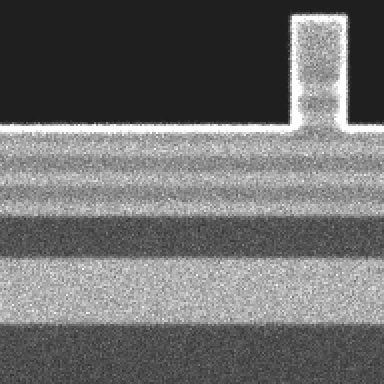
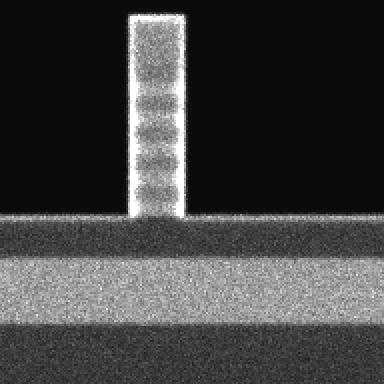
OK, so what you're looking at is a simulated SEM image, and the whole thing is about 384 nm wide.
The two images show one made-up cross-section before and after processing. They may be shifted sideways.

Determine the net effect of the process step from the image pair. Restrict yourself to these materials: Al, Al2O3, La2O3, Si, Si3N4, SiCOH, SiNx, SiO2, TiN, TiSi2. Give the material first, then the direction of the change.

Si3N4 and SiO2: removed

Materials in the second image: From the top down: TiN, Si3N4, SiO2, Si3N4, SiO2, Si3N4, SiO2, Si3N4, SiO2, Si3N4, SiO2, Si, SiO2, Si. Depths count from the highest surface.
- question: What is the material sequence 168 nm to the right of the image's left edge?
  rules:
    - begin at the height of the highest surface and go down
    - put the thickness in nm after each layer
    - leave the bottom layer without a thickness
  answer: TiN 50, Si3N4 16, SiO2 14, Si3N4 16, SiO2 14, Si3N4 16, SiO2 14, Si3N4 16, SiO2 14, Si3N4 16, SiO2 14, Si 42, SiO2 66, Si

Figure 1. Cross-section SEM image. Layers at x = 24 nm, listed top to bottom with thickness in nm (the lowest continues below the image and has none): empty 200, Si 42, SiO2 66, Si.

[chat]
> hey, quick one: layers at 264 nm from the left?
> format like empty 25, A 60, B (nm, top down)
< empty 200, Si 42, SiO2 66, Si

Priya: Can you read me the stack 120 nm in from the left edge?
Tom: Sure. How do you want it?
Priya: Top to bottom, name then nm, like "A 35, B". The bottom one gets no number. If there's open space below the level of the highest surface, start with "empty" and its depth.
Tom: empty 200, Si 42, SiO2 66, Si